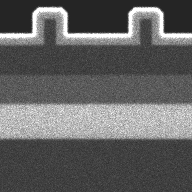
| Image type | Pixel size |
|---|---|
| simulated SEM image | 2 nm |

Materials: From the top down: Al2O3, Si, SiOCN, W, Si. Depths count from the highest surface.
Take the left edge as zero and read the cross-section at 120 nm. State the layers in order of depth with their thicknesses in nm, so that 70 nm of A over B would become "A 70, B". Al2O3 74, Si 60, SiOCN 58, W 70, Si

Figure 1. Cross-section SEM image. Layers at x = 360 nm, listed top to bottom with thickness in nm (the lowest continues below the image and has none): empty 52, Al2O3 22, Si 60, SiOCN 58, W 70, Si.